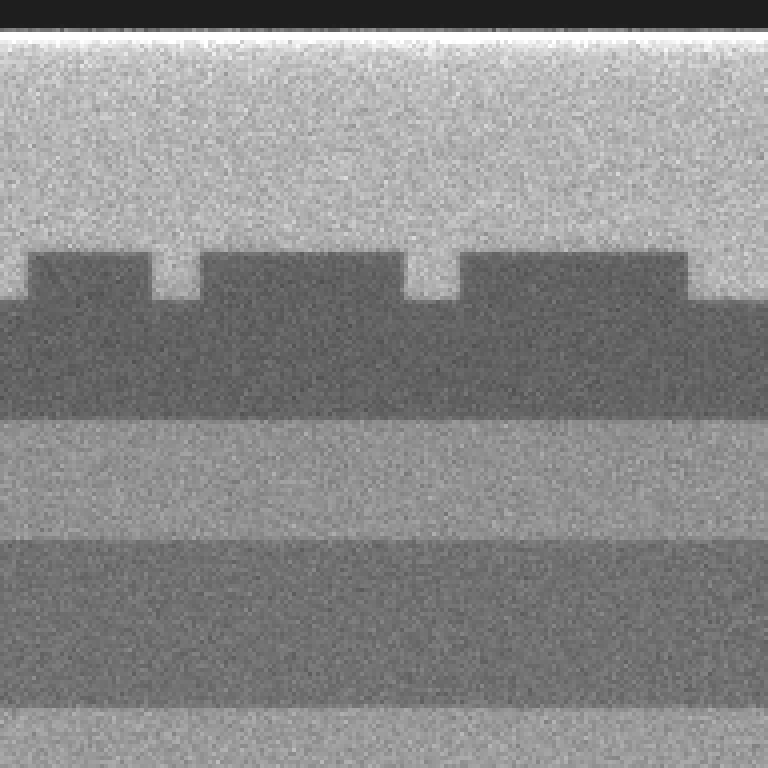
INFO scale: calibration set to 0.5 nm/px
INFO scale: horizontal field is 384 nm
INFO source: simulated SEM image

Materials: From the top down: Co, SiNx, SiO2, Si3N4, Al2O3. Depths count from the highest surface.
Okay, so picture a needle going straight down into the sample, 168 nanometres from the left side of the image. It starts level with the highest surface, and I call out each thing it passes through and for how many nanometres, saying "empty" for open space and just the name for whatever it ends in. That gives Co 110, SiNx 84, SiO2 60, Si3N4 84, Al2O3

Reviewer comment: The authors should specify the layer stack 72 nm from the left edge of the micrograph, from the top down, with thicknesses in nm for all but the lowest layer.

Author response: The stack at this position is Co 110, SiNx 84, SiO2 60, Si3N4 84, Al2O3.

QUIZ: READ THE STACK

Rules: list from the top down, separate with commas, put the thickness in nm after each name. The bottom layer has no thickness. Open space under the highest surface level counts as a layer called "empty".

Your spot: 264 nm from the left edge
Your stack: Co 110, SiNx 84, SiO2 60, Si3N4 84, Al2O3